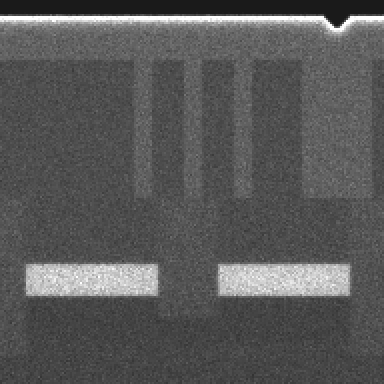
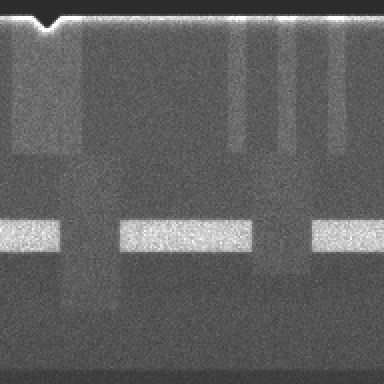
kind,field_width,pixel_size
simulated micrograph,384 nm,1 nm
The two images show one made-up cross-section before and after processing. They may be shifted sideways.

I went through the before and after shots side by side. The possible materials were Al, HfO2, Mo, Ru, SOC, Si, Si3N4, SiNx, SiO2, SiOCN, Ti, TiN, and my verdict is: removed, SiO2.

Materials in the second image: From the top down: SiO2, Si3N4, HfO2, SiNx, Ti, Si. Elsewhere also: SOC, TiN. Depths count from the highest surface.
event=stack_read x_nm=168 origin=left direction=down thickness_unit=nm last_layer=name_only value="SOC 138, Si3N4 66, HfO2 32, SiNx 44, Ti 74, Si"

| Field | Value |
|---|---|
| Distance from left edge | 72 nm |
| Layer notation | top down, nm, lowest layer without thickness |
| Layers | SiO2 138, TiN 158, Ti 58, Si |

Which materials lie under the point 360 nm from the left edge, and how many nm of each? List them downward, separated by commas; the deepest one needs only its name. SOC 138, Si3N4 66, HfO2 32, SiNx 44, Ti 74, Si